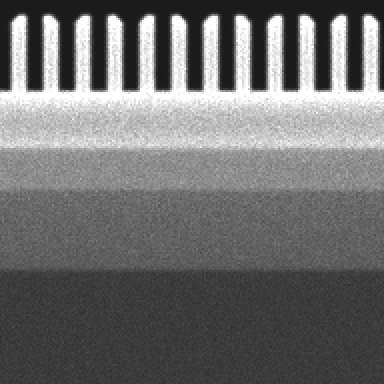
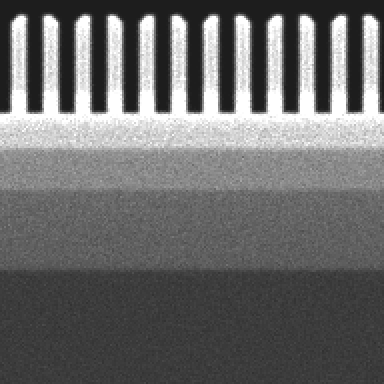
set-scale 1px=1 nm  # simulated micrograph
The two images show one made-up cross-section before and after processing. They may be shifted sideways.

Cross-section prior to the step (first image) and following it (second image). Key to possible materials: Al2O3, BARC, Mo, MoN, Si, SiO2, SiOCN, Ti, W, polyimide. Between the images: W was removed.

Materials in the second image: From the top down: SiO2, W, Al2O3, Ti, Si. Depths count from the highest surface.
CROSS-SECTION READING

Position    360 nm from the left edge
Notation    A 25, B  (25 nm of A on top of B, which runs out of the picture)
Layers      empty 98, W 34, Al2O3 42, Ti 80, Si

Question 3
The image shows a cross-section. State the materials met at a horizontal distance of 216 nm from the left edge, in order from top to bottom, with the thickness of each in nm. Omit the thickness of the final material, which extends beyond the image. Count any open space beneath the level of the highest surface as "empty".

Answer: SiO2 76, W 56, Al2O3 42, Ti 80, Si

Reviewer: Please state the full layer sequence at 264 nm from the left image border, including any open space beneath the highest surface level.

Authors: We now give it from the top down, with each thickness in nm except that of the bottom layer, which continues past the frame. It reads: empty 98, W 34, Al2O3 42, Ti 80, Si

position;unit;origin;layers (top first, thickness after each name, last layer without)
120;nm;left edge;empty 6, SiO2 70, W 56, Al2O3 42, Ti 80, Si